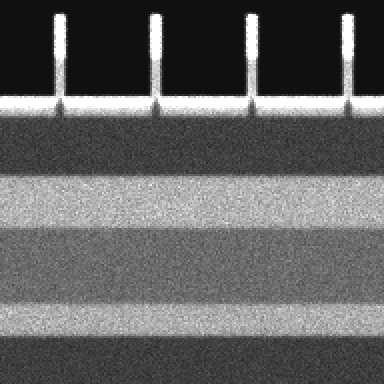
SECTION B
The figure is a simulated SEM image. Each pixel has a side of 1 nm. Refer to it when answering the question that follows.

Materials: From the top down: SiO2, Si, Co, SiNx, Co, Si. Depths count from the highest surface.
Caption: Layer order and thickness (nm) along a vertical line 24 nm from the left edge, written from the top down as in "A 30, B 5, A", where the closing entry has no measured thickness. empty 82, SiO2 18, Si 60, Co 52, SiNx 76, Co 32, Si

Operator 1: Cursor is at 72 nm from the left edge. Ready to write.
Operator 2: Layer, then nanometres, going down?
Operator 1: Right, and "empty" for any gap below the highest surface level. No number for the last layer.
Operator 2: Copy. empty 82, SiO2 18, Si 60, Co 52, SiNx 76, Co 32, Si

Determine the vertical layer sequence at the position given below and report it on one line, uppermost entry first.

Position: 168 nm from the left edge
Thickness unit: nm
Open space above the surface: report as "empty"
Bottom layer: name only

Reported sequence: empty 82, SiO2 18, Si 60, Co 52, SiNx 76, Co 32, Si